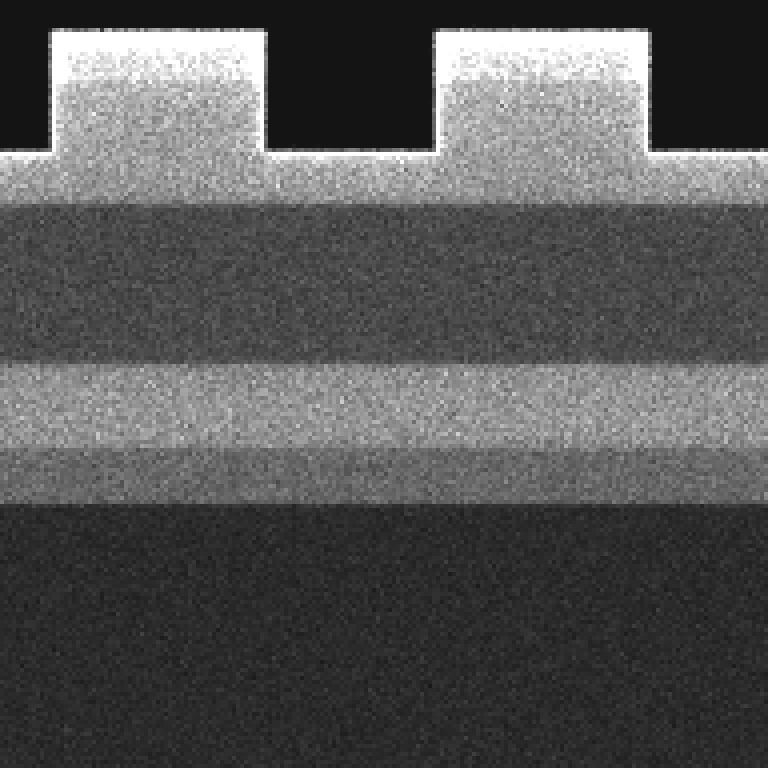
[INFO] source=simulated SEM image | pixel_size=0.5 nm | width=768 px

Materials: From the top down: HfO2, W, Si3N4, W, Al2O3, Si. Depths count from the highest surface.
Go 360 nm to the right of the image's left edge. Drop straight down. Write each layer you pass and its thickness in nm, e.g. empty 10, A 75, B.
empty 60, W 26, Si3N4 80, W 42, Al2O3 28, Si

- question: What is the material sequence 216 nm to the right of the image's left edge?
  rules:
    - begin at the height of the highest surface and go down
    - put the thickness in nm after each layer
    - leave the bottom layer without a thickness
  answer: empty 60, W 26, Si3N4 80, W 42, Al2O3 28, Si